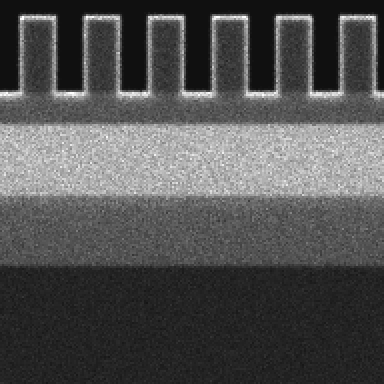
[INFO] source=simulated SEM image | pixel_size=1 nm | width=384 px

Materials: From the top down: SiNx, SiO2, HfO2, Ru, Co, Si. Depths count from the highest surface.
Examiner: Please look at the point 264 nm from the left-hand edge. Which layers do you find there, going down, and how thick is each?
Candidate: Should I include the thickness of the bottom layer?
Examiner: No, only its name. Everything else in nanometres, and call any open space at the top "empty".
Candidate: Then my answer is empty 76, SiO2 32, HfO2 72, Ru 10, Co 60, Si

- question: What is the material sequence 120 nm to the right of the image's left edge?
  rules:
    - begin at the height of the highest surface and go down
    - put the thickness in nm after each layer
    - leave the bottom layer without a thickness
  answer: empty 76, SiO2 32, HfO2 72, Ru 10, Co 60, Si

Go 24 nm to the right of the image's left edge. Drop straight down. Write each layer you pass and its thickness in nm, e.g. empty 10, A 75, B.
SiNx 76, SiO2 32, HfO2 72, Ru 10, Co 60, Si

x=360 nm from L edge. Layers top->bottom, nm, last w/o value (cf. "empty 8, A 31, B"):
SiNx 76, SiO2 32, HfO2 72, Ru 10, Co 60, Si